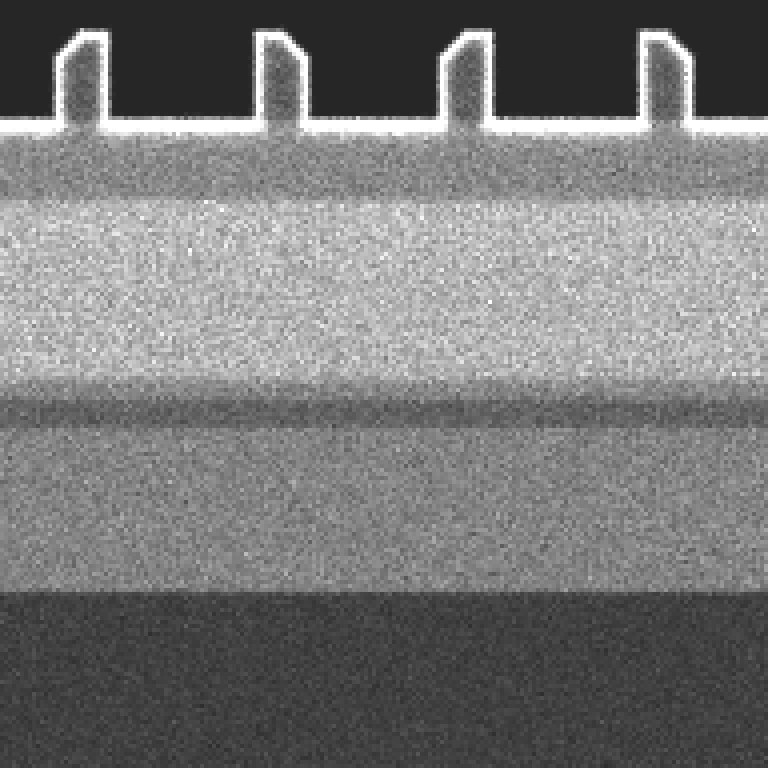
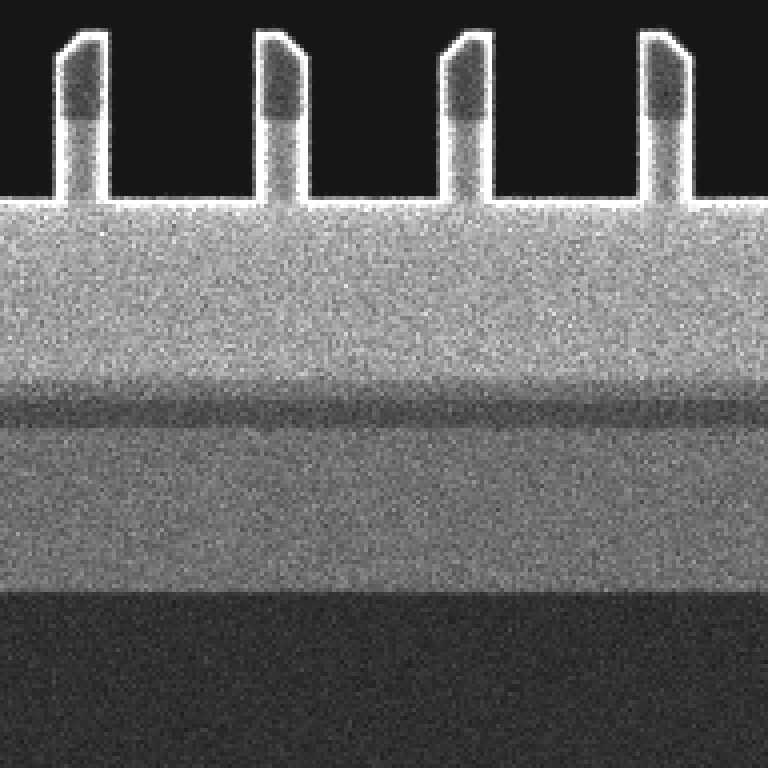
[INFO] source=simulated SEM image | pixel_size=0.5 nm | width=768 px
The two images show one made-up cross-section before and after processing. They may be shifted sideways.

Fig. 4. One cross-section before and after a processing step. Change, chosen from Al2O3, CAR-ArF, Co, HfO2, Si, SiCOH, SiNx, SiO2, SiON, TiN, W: Al2O3 removed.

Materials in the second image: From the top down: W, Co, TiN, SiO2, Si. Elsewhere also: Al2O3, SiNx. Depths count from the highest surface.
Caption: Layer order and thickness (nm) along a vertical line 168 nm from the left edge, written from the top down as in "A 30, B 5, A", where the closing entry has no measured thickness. empty 84, W 90, Co 10, TiN 14, SiO2 82, Si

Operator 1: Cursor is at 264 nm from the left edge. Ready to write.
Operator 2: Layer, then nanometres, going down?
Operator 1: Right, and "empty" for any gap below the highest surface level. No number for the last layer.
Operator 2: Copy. empty 84, W 90, Co 10, TiN 14, SiO2 82, Si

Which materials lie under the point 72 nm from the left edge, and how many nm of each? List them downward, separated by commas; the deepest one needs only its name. empty 84, W 90, Co 10, TiN 14, SiO2 82, Si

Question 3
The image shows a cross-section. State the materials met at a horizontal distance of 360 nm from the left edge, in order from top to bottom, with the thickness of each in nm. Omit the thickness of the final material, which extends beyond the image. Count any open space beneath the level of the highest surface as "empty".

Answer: empty 84, W 90, Co 10, TiN 14, SiO2 82, Si